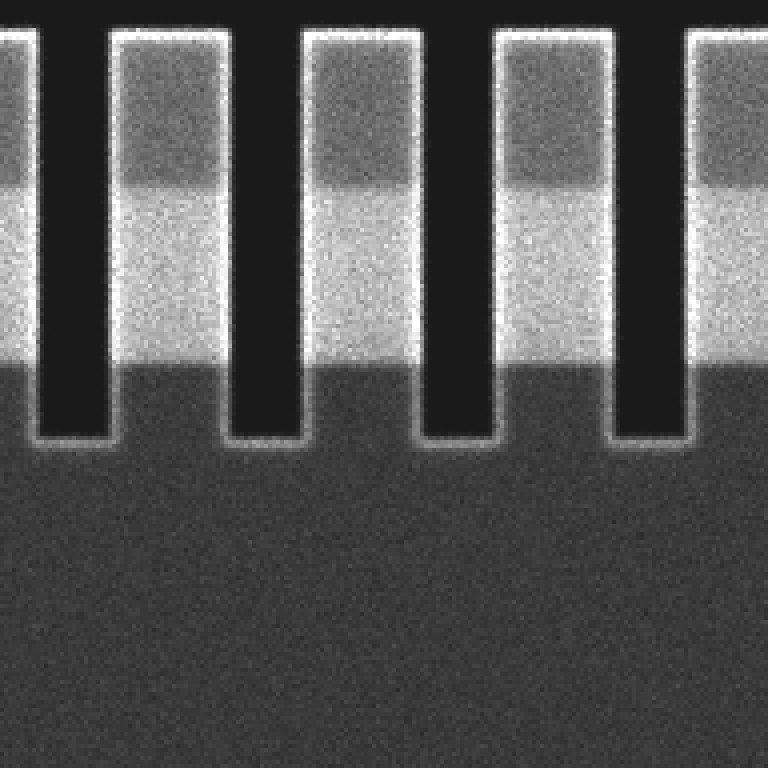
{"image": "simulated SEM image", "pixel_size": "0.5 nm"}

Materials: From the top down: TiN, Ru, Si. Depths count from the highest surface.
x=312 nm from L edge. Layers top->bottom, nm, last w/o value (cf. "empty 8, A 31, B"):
empty 204, Si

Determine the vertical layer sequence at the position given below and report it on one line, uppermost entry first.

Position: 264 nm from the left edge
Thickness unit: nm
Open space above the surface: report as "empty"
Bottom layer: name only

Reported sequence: TiN 78, Ru 88, Si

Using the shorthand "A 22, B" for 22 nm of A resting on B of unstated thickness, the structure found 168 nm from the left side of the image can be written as TiN 78, Ru 88, Si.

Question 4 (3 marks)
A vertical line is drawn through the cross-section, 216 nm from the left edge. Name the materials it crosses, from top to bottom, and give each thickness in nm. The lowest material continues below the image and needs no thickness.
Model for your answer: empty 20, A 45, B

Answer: empty 204, Si